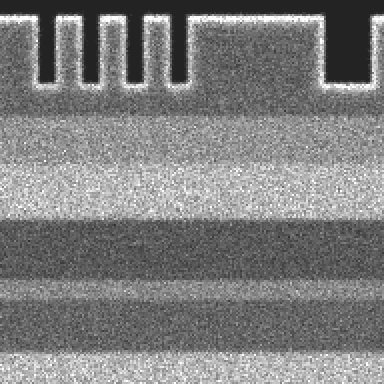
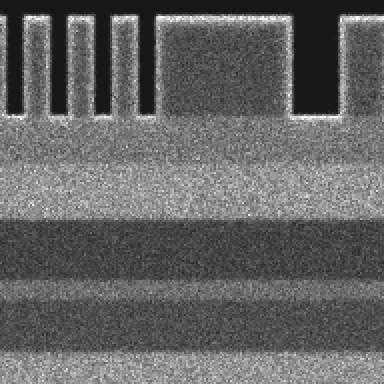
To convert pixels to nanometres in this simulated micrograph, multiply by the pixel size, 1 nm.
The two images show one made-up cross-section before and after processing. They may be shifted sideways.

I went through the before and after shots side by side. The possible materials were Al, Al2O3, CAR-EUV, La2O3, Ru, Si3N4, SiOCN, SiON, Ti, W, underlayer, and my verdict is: removed, underlayer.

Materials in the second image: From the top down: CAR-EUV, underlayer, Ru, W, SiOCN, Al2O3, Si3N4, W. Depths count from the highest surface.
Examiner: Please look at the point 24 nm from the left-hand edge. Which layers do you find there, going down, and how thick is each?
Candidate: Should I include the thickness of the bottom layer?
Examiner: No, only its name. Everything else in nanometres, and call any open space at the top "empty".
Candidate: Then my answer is CAR-EUV 68, underlayer 32, Ru 48, W 56, SiOCN 60, Al2O3 20, Si3N4 52, W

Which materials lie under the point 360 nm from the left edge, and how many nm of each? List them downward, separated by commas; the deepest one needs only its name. CAR-EUV 68, underlayer 32, Ru 48, W 56, SiOCN 60, Al2O3 20, Si3N4 52, W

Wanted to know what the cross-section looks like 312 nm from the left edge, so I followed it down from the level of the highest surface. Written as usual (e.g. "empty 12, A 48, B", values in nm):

empty 100, Ru 48, W 56, SiOCN 60, Al2O3 20, Si3N4 52, W